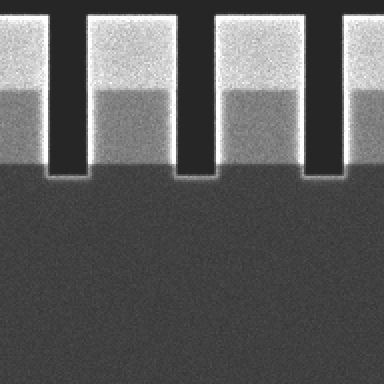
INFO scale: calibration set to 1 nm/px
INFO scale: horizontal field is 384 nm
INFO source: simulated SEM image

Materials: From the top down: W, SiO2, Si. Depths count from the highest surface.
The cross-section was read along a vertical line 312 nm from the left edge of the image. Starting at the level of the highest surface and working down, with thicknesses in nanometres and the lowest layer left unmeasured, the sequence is empty 160, Si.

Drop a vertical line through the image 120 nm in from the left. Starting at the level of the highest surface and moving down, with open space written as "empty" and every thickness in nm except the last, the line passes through W 74, SiO2 74, Si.